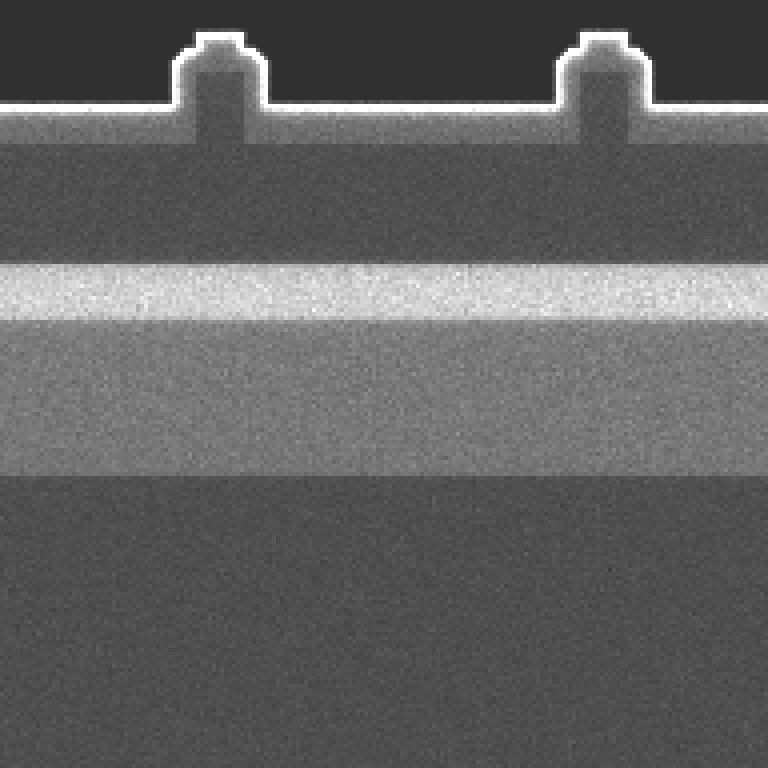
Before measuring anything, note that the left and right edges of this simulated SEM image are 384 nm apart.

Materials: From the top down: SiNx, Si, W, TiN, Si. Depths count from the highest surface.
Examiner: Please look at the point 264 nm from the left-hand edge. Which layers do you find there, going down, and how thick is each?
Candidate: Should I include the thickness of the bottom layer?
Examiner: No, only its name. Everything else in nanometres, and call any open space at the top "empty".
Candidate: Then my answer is empty 36, SiNx 20, Si 60, W 28, TiN 78, Si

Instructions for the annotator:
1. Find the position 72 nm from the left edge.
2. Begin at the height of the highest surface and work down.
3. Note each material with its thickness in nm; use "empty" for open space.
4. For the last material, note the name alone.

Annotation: empty 36, SiNx 20, Si 60, W 28, TiN 78, Si